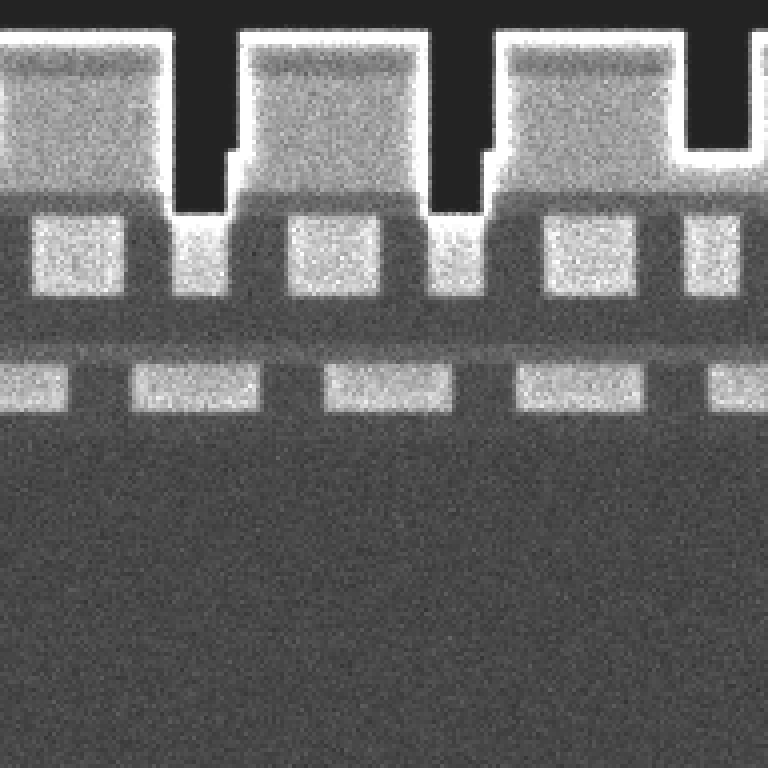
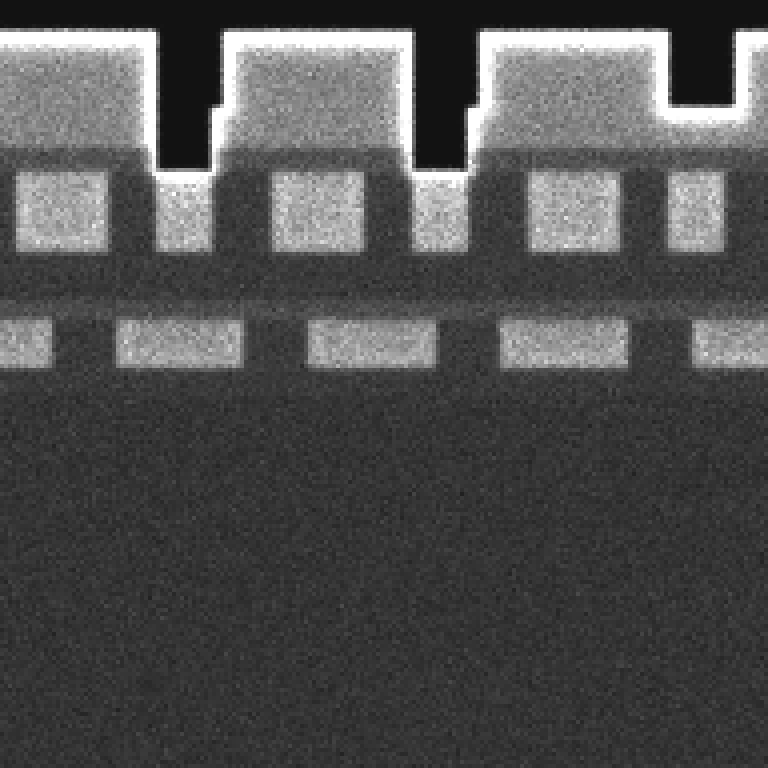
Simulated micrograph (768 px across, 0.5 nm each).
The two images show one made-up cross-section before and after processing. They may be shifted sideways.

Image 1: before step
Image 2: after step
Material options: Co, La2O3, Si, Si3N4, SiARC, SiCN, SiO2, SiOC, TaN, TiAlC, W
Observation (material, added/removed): SiARC, removed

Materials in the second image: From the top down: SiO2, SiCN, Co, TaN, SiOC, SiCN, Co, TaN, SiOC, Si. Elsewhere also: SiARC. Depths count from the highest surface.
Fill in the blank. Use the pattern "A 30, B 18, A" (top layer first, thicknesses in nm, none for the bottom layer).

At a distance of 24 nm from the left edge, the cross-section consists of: SiO2 58, SiCN 12, Co 32, TaN 8, SiOC 24, SiCN 10, TaN 24, SiOC 14, Si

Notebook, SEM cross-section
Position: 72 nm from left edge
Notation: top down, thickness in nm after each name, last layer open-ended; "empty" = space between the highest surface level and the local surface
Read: SiO2 58, SiCN 12, SiOC 64, SiCN 10, Co 16, TaN 8, SiOC 14, Si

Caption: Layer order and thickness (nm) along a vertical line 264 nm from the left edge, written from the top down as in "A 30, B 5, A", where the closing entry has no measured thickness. SiO2 58, SiCN 12, TaN 40, SiOC 24, SiCN 10, Co 16, TaN 8, SiOC 14, Si